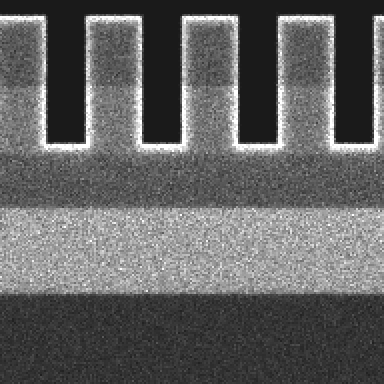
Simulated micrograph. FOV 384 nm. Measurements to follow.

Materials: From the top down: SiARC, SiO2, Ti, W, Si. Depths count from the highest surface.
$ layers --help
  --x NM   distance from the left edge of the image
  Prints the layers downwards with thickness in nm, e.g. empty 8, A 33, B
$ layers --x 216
SiARC 70, SiO2 68, Ti 54, W 86, Si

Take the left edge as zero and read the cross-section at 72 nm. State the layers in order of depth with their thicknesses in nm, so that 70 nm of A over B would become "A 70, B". empty 128, SiO2 10, Ti 54, W 86, Si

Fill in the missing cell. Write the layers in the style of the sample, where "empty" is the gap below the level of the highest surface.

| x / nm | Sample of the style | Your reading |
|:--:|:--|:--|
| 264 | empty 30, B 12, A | empty 128, SiO2 10, Ti 54, W 86, Si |